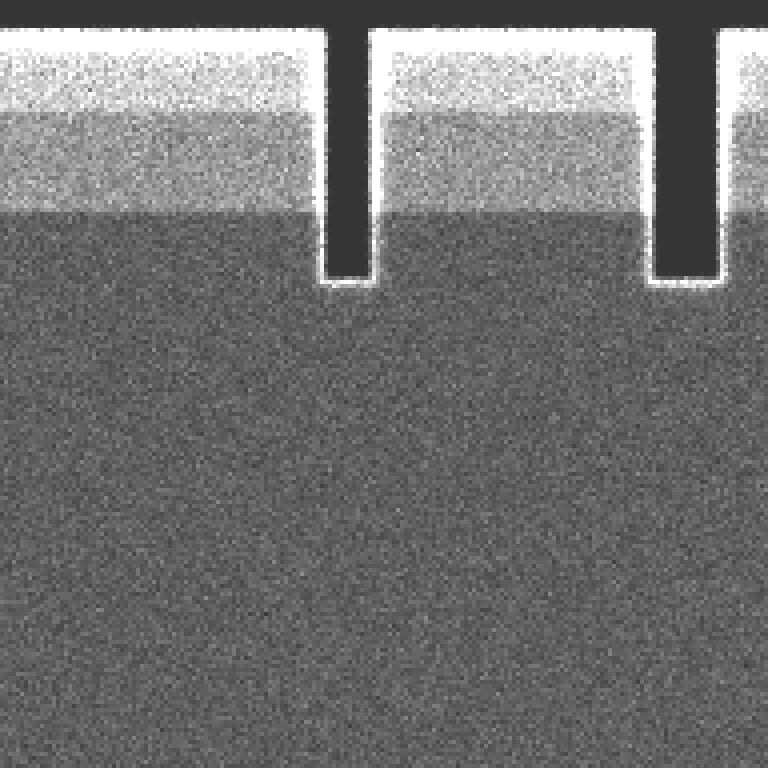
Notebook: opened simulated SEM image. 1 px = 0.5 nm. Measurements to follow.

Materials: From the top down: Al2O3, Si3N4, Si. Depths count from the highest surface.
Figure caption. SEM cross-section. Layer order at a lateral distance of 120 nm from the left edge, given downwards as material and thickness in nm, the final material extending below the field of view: Al2O3 40, Si3N4 50, Si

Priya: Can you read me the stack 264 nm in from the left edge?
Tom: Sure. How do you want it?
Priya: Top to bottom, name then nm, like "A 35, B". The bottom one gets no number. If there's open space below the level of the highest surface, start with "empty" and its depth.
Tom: Al2O3 40, Si3N4 50, Si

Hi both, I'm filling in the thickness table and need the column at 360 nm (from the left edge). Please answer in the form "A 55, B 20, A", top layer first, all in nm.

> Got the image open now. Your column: Al2O3 40, Si3N4 50, Si